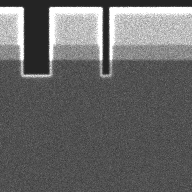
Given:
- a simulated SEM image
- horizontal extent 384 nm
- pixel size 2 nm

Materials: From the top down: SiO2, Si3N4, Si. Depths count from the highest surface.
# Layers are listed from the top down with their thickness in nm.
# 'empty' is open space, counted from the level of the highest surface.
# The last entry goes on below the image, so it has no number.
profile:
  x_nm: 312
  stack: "SiO2 74, Si3N4 30, Si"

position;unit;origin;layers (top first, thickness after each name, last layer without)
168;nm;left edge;SiO2 74, Si3N4 30, Si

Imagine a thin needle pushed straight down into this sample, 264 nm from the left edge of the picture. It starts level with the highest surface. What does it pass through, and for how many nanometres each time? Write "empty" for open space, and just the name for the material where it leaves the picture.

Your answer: SiO2 74, Si3N4 30, Si